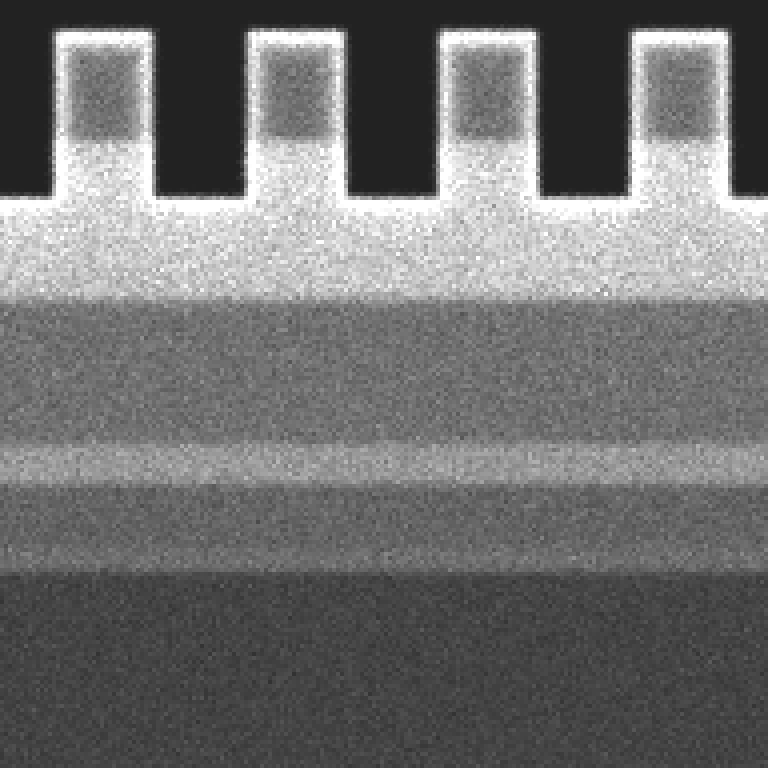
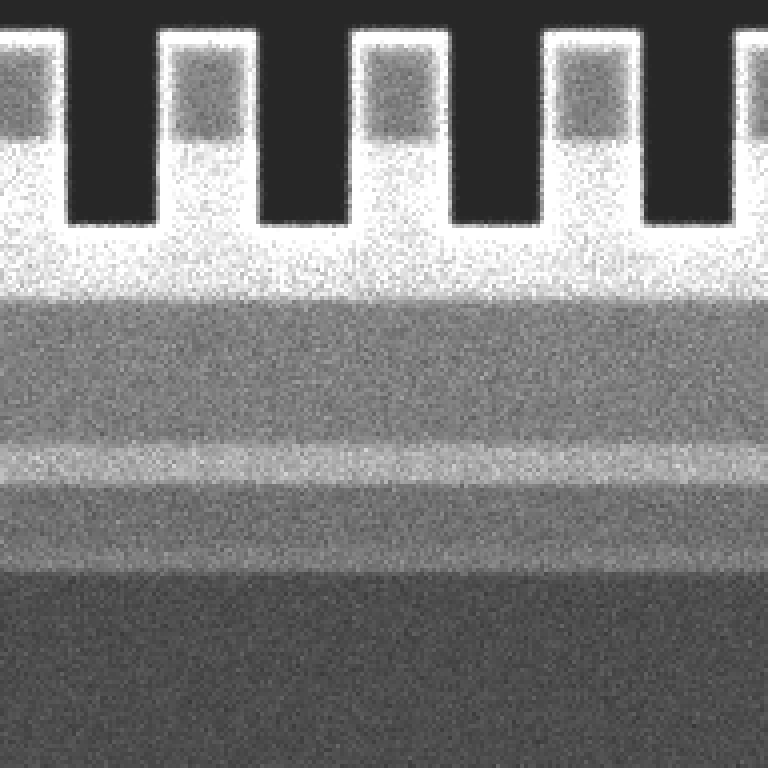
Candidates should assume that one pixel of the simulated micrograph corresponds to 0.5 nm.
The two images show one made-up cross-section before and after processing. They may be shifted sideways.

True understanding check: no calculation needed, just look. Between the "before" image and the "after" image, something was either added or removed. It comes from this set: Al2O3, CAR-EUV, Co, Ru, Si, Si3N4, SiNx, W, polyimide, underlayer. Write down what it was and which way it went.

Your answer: Ru (removed)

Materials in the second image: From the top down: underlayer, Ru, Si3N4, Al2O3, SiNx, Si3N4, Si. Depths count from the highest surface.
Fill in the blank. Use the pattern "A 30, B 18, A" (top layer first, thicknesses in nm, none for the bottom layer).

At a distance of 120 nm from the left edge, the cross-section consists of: underlayer 54, Ru 80, Si3N4 72, Al2O3 20, SiNx 32, Si3N4 12, Si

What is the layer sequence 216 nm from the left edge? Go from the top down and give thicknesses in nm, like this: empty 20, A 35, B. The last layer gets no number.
underlayer 54, Ru 80, Si3N4 72, Al2O3 20, SiNx 32, Si3N4 12, Si